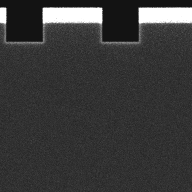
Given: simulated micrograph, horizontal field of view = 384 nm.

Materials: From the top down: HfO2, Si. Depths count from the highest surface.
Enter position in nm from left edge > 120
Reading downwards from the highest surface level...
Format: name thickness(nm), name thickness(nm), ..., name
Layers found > HfO2 30, Si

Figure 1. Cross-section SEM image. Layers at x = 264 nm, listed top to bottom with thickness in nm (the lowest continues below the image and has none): empty 68, Si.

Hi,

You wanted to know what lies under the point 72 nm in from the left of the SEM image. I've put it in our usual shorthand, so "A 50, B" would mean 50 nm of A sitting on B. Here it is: empty 68, Si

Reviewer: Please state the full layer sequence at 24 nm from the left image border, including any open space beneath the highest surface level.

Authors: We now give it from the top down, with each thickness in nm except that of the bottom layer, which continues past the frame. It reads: empty 68, Si